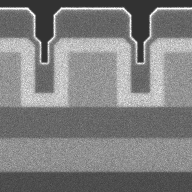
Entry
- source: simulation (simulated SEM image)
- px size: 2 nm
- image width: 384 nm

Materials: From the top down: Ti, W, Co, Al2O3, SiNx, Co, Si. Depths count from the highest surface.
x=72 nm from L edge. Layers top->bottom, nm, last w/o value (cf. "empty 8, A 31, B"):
empty 60, Ti 110, W 28, SiNx 62, Co 68, Si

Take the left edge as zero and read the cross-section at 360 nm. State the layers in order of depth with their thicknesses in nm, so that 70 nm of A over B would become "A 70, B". Ti 60, W 28, Co 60, Al2O3 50, SiNx 62, Co 68, Si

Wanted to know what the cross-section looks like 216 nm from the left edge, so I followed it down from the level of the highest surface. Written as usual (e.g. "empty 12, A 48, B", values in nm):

Ti 60, W 28, Co 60, Al2O3 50, SiNx 62, Co 68, Si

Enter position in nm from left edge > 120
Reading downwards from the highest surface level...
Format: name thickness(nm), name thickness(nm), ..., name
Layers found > empty 2, Ti 60, W 136, SiNx 62, Co 68, Si